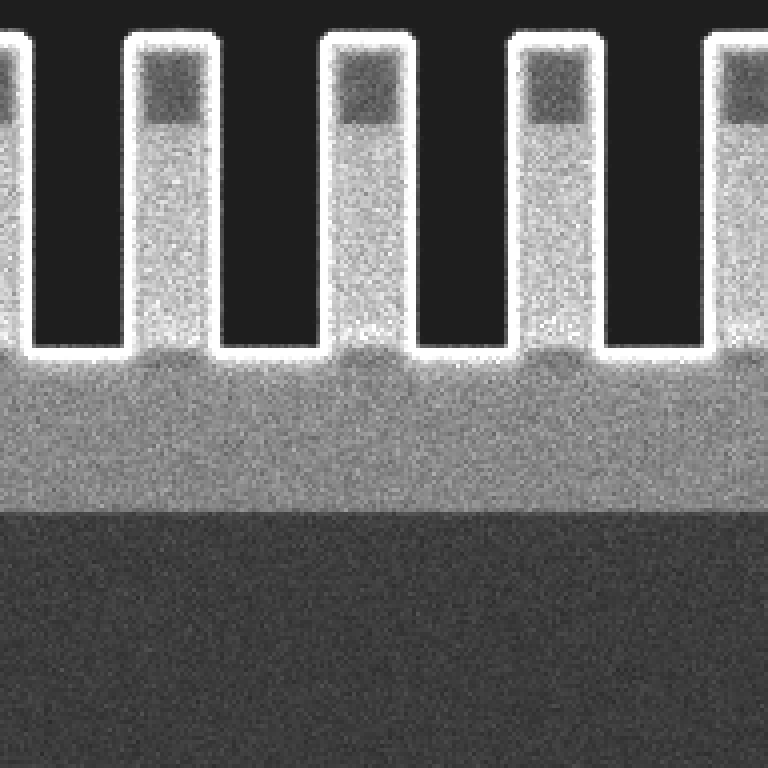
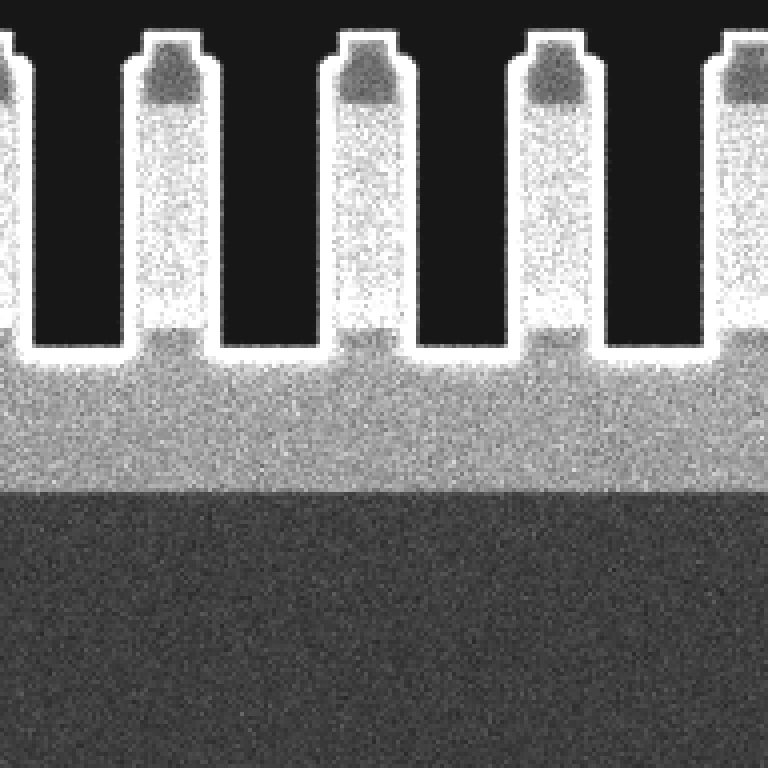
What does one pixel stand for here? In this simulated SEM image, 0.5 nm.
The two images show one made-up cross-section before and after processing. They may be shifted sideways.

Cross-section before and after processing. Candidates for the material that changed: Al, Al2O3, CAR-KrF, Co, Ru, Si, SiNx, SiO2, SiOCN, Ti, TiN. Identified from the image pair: SiO2 (removed).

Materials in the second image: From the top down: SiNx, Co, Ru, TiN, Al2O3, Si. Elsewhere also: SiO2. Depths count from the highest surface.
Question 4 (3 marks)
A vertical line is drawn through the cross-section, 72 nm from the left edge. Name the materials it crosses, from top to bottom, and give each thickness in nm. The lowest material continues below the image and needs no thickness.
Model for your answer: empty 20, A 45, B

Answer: SiNx 36, Co 98, Ru 14, TiN 10, Al2O3 72, Si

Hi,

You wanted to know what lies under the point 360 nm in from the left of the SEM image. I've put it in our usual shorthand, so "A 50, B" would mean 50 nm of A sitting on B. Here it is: empty 12, SiO2 146, Al2O3 72, Si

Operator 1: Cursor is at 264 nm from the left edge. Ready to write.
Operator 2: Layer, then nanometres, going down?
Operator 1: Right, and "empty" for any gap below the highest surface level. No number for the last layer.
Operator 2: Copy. SiNx 36, Co 98, Ru 14, TiN 10, Al2O3 72, Si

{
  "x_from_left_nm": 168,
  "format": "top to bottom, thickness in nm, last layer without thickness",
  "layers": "empty 12, SiO2 146, Al2O3 72, Si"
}